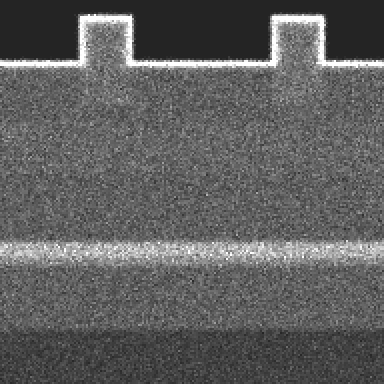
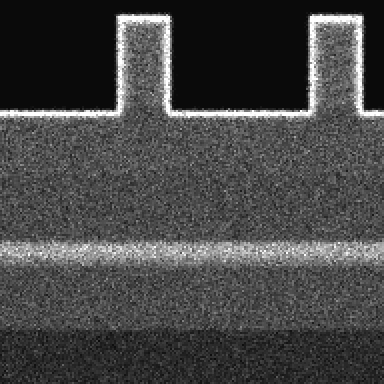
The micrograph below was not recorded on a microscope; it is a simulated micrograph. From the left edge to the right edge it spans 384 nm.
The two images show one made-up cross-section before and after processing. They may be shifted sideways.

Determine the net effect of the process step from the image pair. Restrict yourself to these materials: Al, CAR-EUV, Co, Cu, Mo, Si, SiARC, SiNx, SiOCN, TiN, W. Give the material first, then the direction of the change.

SiNx: removed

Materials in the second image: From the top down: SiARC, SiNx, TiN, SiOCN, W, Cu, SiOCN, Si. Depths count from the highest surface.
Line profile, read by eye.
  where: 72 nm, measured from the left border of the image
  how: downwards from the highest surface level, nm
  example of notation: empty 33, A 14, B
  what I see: empty 96, SiNx 10, TiN 52, SiOCN 68, W 16, Cu 8, SiOCN 64, Si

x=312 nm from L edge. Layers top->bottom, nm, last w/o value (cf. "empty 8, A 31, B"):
SiARC 90, SiNx 16, TiN 52, SiOCN 68, W 16, Cu 8, SiOCN 64, Si